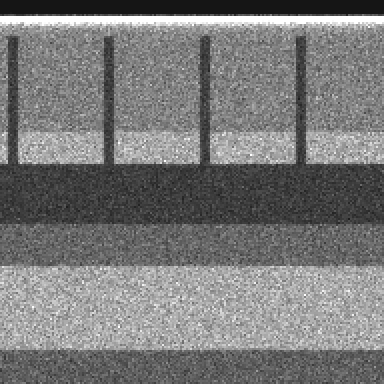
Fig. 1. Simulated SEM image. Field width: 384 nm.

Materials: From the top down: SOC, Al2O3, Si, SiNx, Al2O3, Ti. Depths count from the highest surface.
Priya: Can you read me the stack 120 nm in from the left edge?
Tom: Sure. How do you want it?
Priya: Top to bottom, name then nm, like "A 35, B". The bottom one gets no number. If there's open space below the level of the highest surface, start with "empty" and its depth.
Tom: SOC 116, Al2O3 32, Si 60, SiNx 42, Al2O3 84, Ti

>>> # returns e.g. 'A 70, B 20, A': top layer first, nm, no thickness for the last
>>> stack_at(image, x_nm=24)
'SOC 116, Al2O3 32, Si 60, SiNx 42, Al2O3 84, Ti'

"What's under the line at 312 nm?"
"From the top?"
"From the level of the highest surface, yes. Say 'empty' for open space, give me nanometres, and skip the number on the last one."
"SOC 116, Al2O3 32, Si 60, SiNx 42, Al2O3 84, Ti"